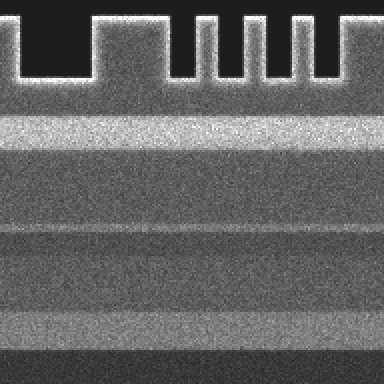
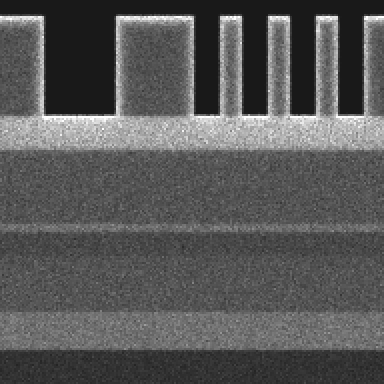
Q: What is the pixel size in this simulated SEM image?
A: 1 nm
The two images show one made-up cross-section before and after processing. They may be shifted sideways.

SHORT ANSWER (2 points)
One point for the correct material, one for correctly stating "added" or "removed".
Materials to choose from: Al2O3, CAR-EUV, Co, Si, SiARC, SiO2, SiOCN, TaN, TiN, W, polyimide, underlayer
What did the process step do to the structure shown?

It removed underlayer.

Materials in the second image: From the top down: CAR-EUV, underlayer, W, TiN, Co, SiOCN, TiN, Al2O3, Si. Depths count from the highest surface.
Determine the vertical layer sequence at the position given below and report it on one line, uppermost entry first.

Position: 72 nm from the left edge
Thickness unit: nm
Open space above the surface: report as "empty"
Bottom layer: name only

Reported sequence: empty 100, W 34, TiN 74, Co 8, SiOCN 24, TiN 56, Al2O3 38, Si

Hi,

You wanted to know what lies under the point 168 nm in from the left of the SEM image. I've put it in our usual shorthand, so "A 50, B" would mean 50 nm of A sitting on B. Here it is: CAR-EUV 62, underlayer 38, W 34, TiN 74, Co 8, SiOCN 24, TiN 56, Al2O3 38, Si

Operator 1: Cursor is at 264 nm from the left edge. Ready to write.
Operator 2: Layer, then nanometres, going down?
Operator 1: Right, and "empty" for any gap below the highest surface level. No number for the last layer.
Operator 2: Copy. empty 100, W 34, TiN 74, Co 8, SiOCN 24, TiN 56, Al2O3 38, Si